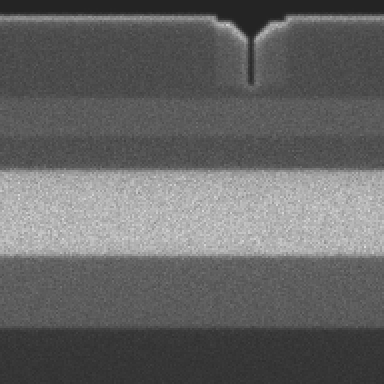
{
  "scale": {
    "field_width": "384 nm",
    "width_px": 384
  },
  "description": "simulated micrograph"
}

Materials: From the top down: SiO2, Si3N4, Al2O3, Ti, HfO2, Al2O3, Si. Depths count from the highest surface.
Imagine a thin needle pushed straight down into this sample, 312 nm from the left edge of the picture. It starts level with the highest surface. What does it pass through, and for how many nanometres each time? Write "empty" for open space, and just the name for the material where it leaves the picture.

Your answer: Si3N4 82, Al2O3 38, Ti 34, HfO2 86, Al2O3 72, Si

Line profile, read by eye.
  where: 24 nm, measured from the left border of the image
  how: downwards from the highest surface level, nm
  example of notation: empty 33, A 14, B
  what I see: Si3N4 82, Al2O3 38, Ti 34, HfO2 86, Al2O3 72, Si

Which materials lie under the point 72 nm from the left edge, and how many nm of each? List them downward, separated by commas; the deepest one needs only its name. Si3N4 82, Al2O3 38, Ti 34, HfO2 86, Al2O3 72, Si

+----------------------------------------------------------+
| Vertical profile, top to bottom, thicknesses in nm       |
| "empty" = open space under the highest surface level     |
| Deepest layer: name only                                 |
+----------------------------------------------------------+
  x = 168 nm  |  Si3N4 82, Al2O3 38, Ti 34, HfO2 86, Al2O3 72, Si